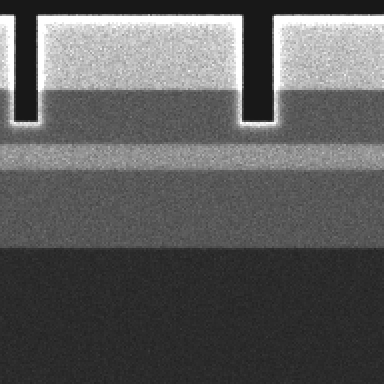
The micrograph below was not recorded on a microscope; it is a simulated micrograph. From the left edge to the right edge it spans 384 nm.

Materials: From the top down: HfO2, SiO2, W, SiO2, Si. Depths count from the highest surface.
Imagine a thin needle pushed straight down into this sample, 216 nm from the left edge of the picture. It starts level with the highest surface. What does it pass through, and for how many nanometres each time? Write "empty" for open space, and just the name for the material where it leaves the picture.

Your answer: HfO2 74, SiO2 54, W 26, SiO2 78, Si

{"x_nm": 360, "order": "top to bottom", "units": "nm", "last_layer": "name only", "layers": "HfO2 74, SiO2 54, W 26, SiO2 78, Si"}